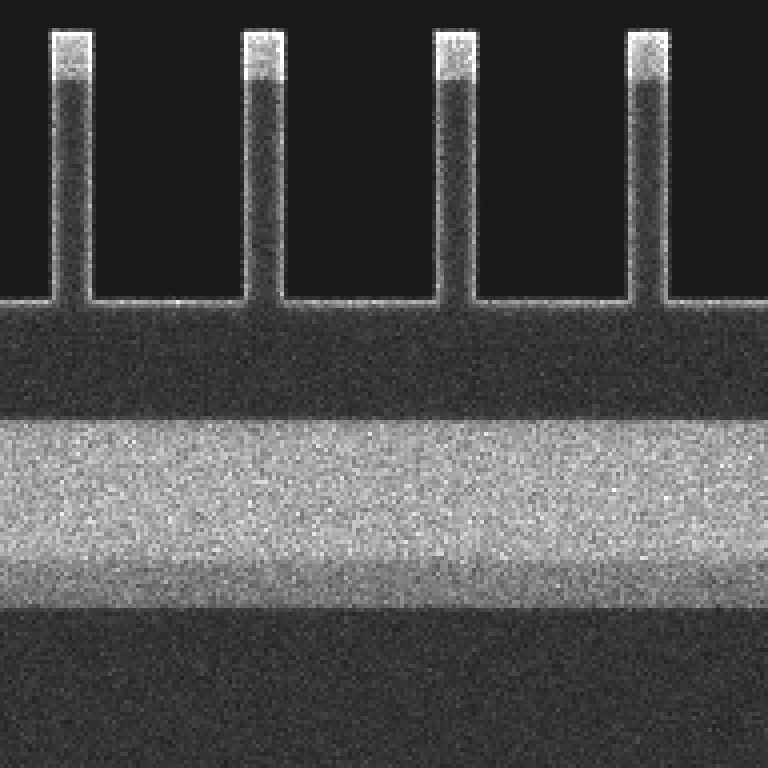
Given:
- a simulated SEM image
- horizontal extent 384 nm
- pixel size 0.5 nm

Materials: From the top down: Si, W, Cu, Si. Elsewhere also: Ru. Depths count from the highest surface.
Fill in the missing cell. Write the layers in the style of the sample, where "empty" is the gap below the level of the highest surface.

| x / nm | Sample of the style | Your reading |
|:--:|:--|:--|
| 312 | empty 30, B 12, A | empty 134, Si 60, W 70, Cu 24, Si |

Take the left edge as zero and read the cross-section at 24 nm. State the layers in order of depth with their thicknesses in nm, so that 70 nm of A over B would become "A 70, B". empty 134, Si 60, W 70, Cu 24, Si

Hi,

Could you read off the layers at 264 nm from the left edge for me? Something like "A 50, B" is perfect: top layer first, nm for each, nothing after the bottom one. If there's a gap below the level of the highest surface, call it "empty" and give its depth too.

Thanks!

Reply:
empty 134, Si 60, W 70, Cu 24, Si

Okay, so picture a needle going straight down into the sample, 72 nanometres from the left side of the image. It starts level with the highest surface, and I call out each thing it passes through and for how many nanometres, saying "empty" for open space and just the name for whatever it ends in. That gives empty 134, Si 60, W 70, Cu 24, Si